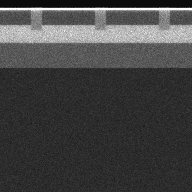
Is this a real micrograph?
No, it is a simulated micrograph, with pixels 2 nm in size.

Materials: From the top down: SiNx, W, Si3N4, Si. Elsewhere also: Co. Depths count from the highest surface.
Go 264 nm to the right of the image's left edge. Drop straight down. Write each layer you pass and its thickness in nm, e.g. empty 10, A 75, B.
SiNx 34, W 36, Si3N4 50, Si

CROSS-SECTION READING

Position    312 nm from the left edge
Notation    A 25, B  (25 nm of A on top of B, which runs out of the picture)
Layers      SiNx 34, W 36, Si3N4 50, Si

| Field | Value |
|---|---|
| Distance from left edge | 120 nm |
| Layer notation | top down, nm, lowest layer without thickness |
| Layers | SiNx 34, W 36, Si3N4 50, Si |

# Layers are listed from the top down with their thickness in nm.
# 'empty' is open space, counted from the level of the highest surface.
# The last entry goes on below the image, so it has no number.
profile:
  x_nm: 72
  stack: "Co 44, W 26, Si3N4 50, Si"